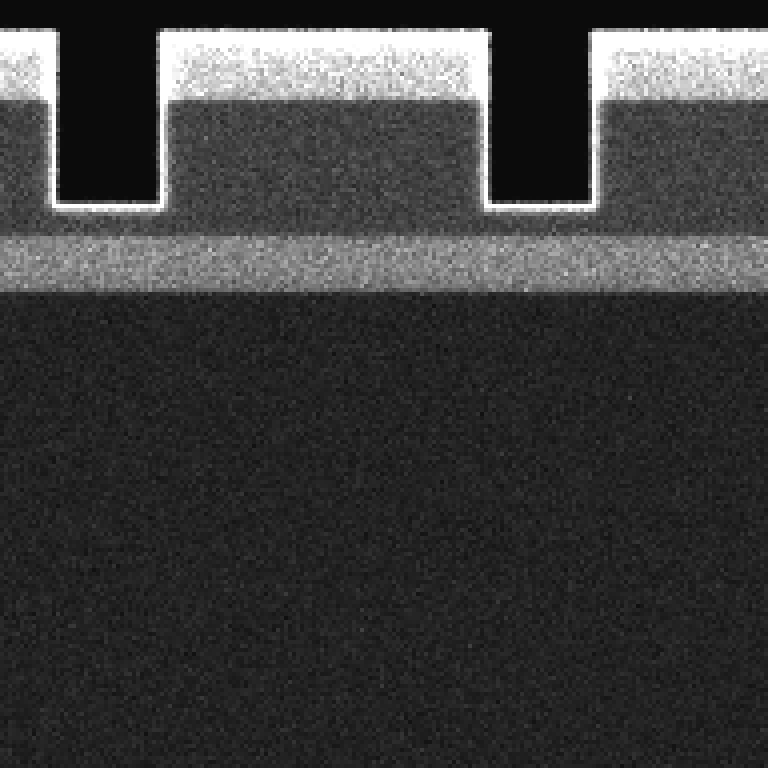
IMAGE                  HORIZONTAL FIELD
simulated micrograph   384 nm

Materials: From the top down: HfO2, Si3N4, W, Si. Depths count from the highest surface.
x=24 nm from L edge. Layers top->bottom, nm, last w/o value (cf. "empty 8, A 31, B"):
HfO2 34, Si3N4 68, W 28, Si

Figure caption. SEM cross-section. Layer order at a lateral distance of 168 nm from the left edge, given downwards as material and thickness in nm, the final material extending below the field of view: HfO2 34, Si3N4 68, W 28, Si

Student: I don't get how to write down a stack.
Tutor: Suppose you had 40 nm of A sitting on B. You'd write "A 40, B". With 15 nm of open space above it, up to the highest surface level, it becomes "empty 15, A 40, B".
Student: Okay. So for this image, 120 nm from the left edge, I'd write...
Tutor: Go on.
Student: HfO2 34, Si3N4 68, W 28, Si